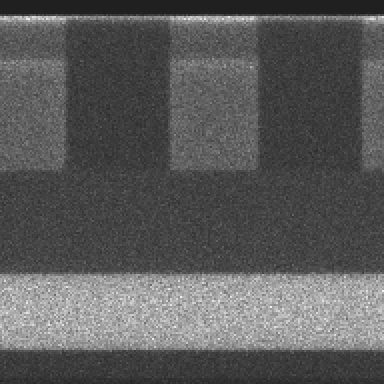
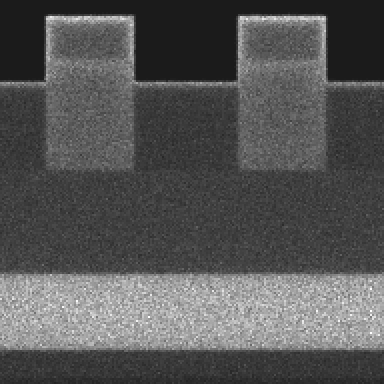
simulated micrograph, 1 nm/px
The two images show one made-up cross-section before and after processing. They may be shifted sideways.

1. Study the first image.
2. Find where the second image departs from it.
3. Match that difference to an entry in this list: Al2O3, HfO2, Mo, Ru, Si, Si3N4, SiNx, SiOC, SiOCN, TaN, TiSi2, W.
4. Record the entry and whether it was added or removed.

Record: SiNx / removed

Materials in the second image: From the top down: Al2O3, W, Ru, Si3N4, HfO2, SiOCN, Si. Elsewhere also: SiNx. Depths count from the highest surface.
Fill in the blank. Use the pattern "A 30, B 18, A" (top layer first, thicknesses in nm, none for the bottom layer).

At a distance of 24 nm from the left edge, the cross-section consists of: empty 66, SiNx 88, Si3N4 104, HfO2 76, SiOCN 28, Si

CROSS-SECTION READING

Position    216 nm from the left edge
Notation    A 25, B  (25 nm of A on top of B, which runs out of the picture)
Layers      empty 66, SiNx 88, Si3N4 104, HfO2 76, SiOCN 28, Si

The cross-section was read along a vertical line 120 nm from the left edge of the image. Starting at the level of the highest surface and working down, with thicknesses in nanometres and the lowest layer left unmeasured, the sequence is Al2O3 44, W 94, Ru 16, Si3N4 104, HfO2 76, SiOCN 28, Si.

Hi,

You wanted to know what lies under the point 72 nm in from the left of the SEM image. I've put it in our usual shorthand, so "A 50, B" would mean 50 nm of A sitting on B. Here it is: Al2O3 44, W 94, Ru 16, Si3N4 104, HfO2 76, SiOCN 28, Si